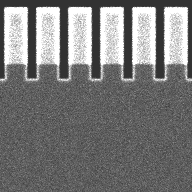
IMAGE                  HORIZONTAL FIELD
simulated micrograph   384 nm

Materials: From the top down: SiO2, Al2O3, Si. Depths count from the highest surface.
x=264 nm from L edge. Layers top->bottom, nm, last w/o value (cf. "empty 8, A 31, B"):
empty 142, Si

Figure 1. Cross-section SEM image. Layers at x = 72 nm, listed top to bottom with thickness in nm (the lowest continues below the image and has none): empty 142, Si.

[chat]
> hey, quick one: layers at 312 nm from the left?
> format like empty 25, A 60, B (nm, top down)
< empty 142, Si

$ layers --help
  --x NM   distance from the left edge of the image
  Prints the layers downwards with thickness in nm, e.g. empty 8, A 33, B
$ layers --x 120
empty 142, Si